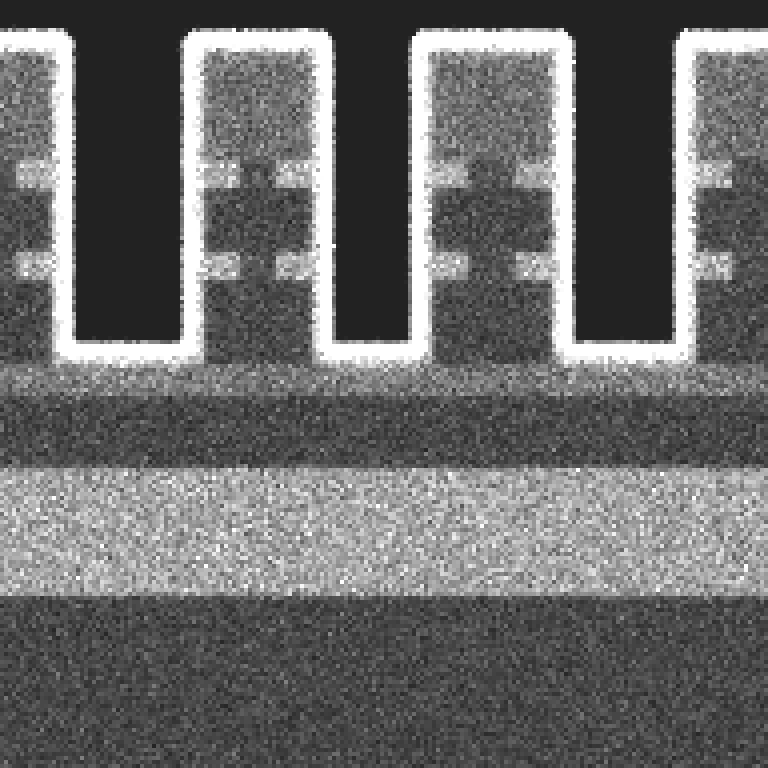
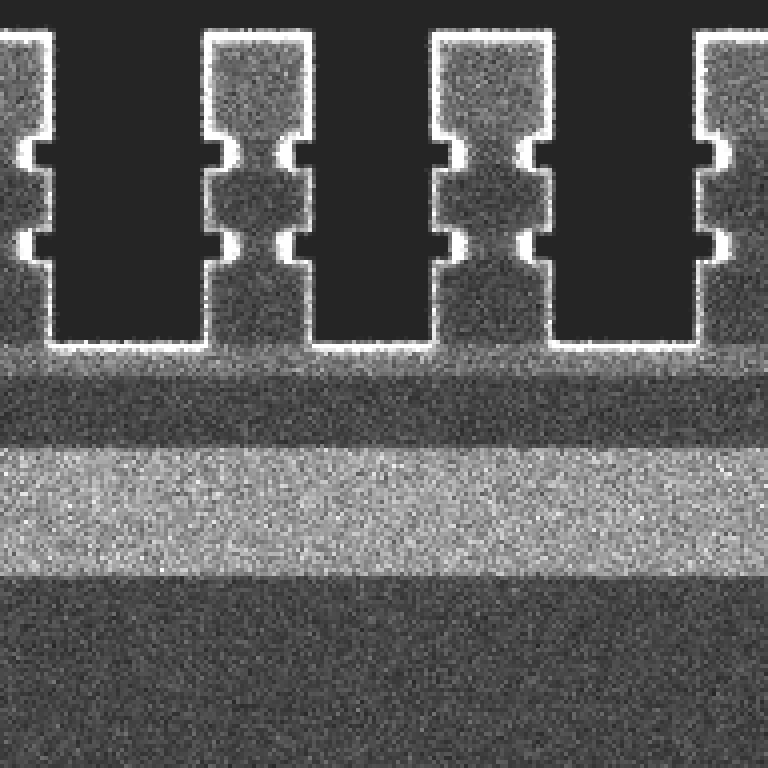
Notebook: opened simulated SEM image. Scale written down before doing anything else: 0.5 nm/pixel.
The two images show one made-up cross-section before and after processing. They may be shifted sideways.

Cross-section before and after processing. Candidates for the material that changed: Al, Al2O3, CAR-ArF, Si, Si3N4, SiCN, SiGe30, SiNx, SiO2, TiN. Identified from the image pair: Al2O3 (removed).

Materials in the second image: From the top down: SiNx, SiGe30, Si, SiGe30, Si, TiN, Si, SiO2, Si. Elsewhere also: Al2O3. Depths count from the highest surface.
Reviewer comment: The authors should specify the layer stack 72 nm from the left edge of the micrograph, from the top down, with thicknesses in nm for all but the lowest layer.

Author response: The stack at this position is empty 156, TiN 16, Si 36, SiO2 64, Si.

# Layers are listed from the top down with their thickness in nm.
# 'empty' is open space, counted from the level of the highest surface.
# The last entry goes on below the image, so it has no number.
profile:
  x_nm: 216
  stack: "SiNx 54, empty 14, Si 32, empty 14, Si 42, TiN 16, Si 36, SiO2 64, Si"